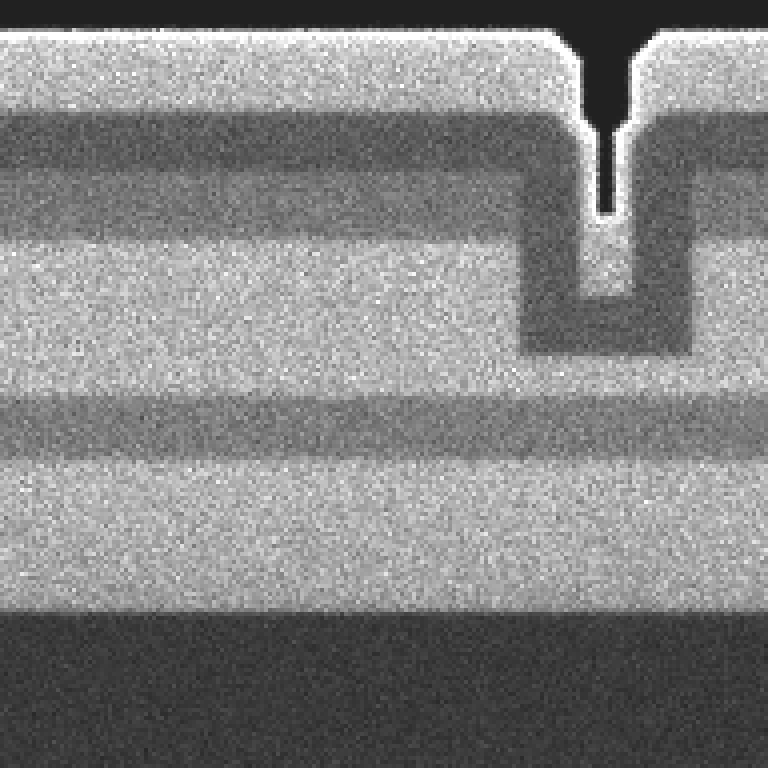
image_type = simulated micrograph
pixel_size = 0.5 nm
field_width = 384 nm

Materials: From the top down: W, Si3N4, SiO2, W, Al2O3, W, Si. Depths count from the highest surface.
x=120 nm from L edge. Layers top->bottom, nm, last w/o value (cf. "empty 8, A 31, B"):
W 40, Si3N4 30, SiO2 34, W 78, Al2O3 32, W 76, Si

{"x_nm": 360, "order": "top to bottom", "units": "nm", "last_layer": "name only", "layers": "W 40, Si3N4 30, SiO2 34, W 78, Al2O3 32, W 76, Si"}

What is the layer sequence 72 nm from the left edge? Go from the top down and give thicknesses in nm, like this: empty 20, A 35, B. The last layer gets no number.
W 40, Si3N4 30, SiO2 34, W 78, Al2O3 32, W 76, Si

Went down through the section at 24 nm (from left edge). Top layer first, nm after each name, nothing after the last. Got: W 40, Si3N4 30, SiO2 34, W 78, Al2O3 32, W 76, Si